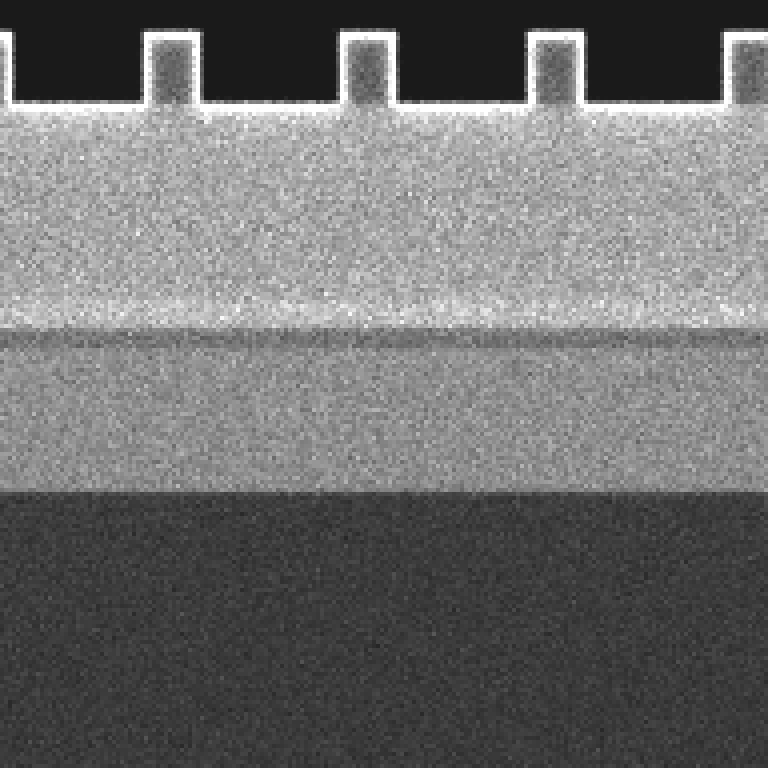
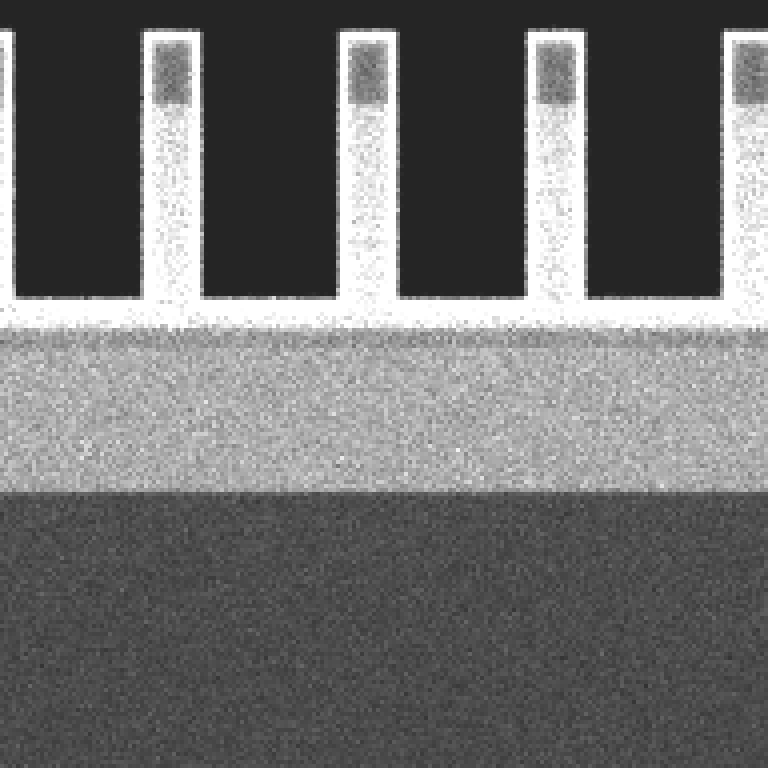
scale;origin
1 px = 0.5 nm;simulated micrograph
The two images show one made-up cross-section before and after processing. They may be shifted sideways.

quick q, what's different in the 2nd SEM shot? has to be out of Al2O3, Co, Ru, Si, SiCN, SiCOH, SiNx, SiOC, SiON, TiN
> Co removed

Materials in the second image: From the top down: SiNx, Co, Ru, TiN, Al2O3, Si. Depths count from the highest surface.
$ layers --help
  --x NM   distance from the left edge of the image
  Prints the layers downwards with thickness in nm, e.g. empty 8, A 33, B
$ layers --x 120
empty 134, Ru 14, TiN 10, Al2O3 72, Si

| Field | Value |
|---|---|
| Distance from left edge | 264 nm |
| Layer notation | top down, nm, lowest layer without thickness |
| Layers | SiNx 36, Co 98, Ru 14, TiN 10, Al2O3 72, Si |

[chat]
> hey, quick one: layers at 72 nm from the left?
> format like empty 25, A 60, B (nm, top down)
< SiNx 36, Co 98, Ru 14, TiN 10, Al2O3 72, Si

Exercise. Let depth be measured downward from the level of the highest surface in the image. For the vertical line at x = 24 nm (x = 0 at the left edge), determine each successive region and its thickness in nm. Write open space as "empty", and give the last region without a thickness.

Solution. empty 134, Ru 14, TiN 10, Al2O3 72, Si